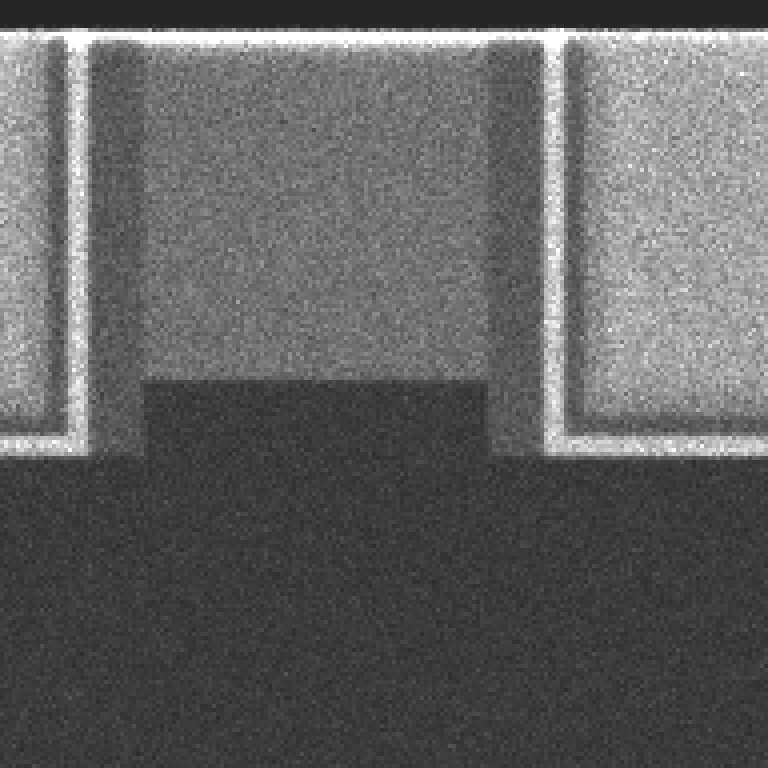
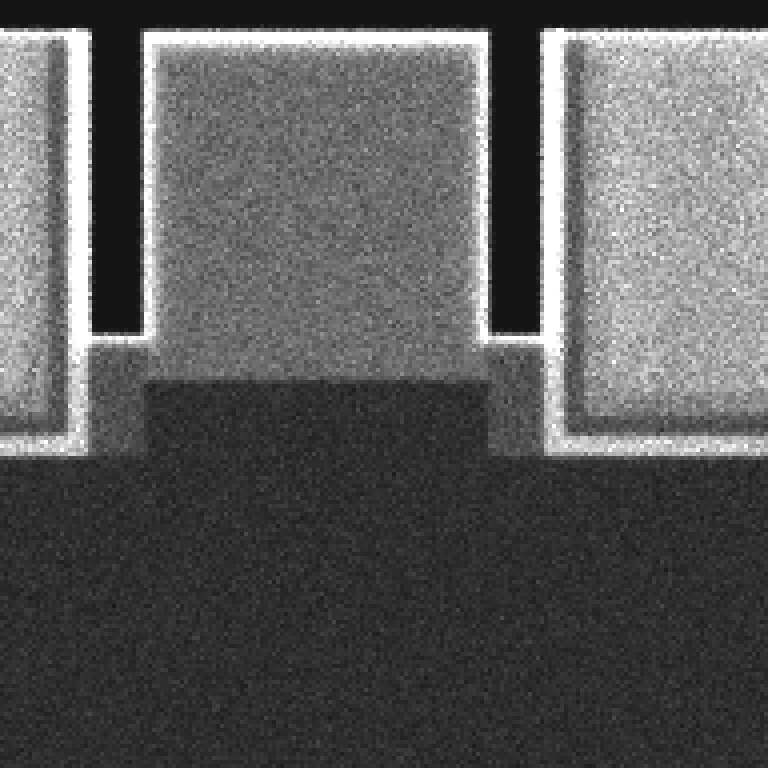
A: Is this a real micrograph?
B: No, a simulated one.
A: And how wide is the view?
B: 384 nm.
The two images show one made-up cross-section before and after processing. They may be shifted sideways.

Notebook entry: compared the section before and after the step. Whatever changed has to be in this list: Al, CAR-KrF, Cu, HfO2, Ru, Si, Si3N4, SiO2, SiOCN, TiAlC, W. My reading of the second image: Si3N4 removed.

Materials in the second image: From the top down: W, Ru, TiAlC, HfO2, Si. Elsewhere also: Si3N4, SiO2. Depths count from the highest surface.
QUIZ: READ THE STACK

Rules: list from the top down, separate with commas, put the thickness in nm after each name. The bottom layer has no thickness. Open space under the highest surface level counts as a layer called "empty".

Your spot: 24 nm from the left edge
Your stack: TiAlC 202, HfO2 10, Si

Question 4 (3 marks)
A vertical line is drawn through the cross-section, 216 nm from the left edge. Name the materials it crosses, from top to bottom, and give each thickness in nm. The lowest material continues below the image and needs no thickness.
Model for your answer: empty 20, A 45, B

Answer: SiO2 174, Si